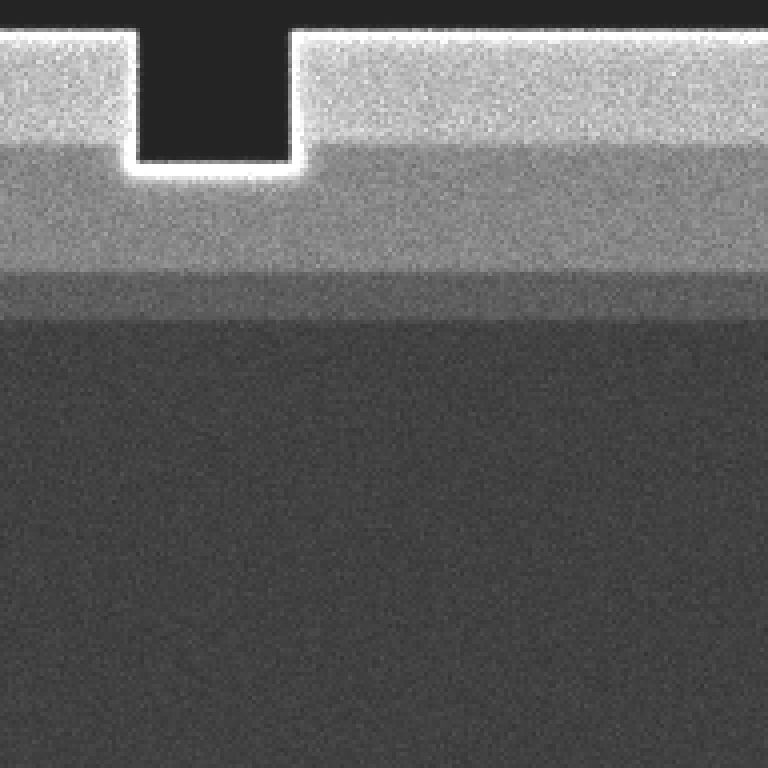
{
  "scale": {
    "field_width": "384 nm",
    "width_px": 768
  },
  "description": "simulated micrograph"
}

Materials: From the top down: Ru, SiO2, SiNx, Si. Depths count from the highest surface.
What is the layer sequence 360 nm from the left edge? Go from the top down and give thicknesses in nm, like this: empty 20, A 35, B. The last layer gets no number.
Ru 56, SiO2 64, SiNx 24, Si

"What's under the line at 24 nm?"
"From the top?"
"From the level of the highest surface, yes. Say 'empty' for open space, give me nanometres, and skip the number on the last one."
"Ru 56, SiO2 64, SiNx 24, Si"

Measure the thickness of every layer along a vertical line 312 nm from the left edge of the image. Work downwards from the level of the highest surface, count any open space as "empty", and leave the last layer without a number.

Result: Ru 56, SiO2 64, SiNx 24, Si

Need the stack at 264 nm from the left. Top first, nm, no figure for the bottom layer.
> Ru 56, SiO2 64, SiNx 24, Si